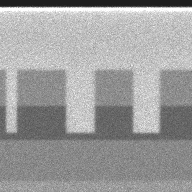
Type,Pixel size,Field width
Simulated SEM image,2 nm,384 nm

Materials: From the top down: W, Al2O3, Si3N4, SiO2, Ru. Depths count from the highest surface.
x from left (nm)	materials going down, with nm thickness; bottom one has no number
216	W 124, Al2O3 72, Si3N4 68, SiO2 82, Ru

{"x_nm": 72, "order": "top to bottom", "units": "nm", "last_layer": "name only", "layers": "W 124, Al2O3 72, Si3N4 68, SiO2 82, Ru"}